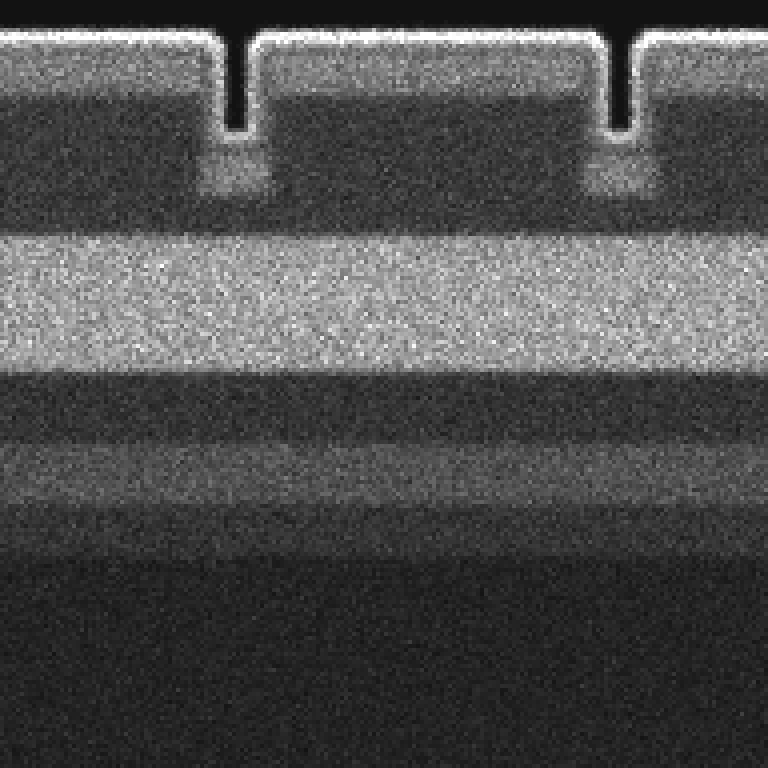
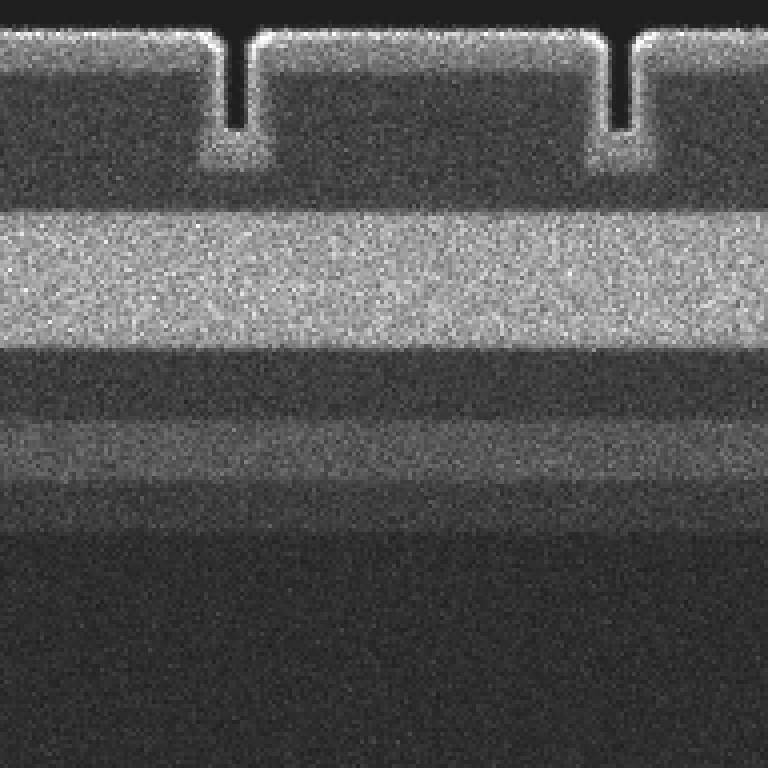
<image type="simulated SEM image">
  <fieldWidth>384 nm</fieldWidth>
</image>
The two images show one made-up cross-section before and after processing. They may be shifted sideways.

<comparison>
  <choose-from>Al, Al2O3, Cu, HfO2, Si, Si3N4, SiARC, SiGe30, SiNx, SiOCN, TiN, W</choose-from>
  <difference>Al2O3 removed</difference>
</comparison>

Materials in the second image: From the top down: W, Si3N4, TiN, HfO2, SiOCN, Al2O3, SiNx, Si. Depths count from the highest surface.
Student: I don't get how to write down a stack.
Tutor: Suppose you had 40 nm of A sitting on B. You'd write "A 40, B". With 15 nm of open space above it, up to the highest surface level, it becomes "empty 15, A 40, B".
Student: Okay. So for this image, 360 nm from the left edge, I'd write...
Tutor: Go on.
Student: W 20, Si3N4 20, TiN 50, HfO2 68, SiOCN 36, Al2O3 30, SiNx 26, Si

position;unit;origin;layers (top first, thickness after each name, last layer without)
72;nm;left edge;W 20, Si3N4 20, TiN 50, HfO2 68, SiOCN 36, Al2O3 30, SiNx 26, Si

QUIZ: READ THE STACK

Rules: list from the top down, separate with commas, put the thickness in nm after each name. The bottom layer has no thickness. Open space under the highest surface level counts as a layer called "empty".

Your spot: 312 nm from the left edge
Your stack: empty 50, W 20, Si3N4 20, HfO2 68, SiOCN 36, Al2O3 30, SiNx 26, Si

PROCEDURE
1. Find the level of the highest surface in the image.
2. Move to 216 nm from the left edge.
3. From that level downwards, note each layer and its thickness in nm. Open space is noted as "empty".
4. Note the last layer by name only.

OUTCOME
W 20, Si3N4 20, TiN 50, HfO2 68, SiOCN 36, Al2O3 30, SiNx 26, Si